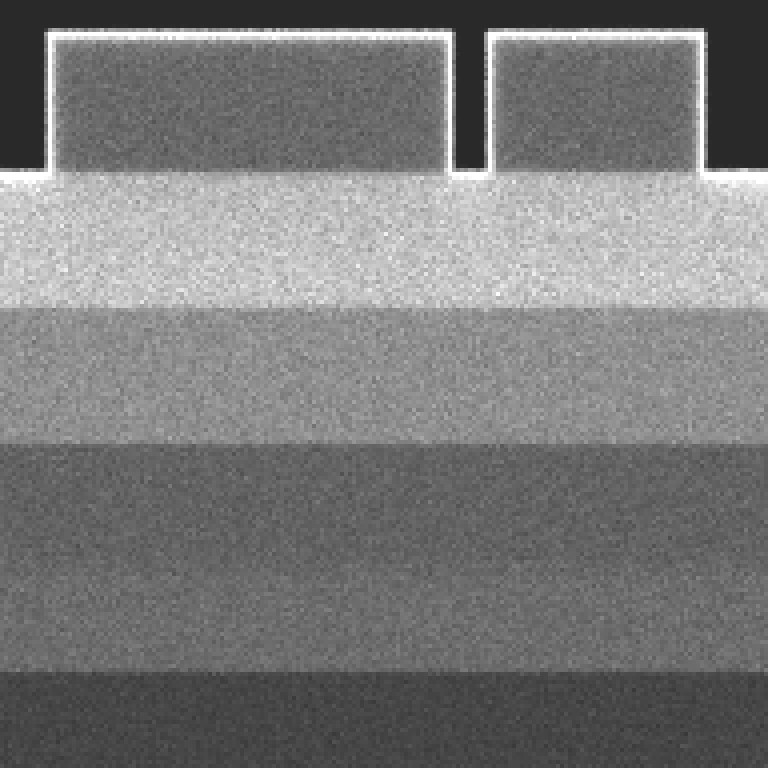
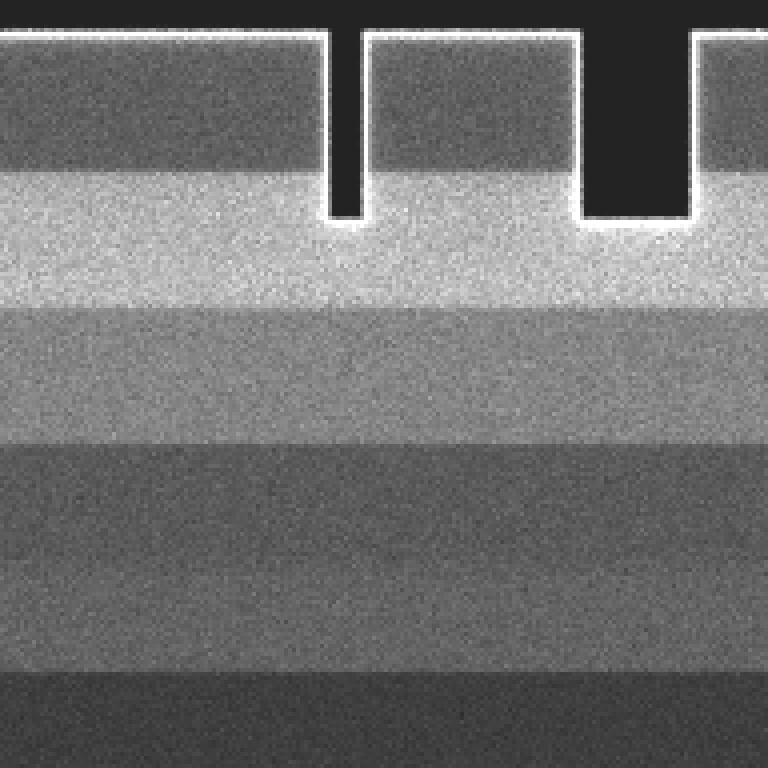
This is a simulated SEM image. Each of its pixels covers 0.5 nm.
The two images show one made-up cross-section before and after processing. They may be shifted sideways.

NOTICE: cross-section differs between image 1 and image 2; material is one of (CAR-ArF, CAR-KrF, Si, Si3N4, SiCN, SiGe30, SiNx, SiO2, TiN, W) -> removed: W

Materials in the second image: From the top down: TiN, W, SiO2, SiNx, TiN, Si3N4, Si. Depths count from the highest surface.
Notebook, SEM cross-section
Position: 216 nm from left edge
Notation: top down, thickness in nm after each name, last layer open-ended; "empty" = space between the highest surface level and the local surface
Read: TiN 70, W 68, SiO2 68, SiNx 58, TiN 8, Si3N4 48, Si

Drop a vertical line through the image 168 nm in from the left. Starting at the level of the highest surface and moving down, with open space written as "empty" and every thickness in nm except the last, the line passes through empty 94, W 44, SiO2 68, SiNx 58, TiN 8, Si3N4 48, Si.